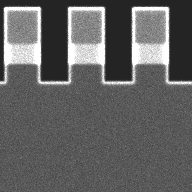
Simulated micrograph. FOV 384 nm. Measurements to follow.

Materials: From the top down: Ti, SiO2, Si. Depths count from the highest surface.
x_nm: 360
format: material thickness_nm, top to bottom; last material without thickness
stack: empty 148, Si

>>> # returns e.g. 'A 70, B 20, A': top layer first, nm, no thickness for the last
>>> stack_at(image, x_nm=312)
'Ti 72, SiO2 40, Si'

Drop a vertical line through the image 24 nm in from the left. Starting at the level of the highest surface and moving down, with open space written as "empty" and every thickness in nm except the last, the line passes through Ti 72, SiO2 40, Si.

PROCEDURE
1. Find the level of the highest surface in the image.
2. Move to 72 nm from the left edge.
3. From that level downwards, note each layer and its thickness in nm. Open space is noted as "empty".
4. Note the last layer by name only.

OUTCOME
Ti 72, SiO2 40, Si